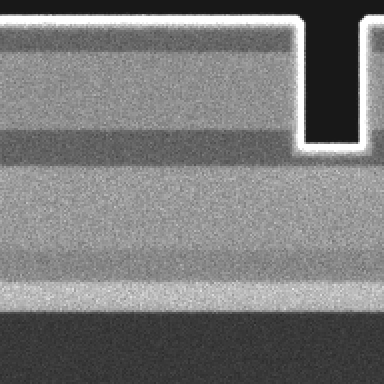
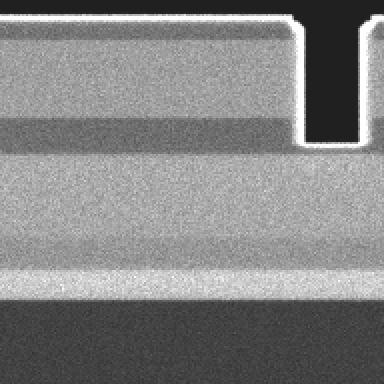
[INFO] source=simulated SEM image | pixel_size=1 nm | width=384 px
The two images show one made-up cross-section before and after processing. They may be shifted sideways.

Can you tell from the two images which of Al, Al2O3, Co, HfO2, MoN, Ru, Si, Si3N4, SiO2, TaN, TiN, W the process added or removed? Yes, it removed SiO2.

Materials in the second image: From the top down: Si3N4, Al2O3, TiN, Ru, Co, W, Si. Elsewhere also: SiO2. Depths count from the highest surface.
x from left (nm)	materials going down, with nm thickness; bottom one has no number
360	empty 12, SiO2 116, TiN 10, Ru 84, Co 32, W 30, Si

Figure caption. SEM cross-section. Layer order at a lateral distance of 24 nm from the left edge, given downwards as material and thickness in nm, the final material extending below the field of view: Si3N4 24, Al2O3 78, TiN 36, Ru 84, Co 32, W 30, Si